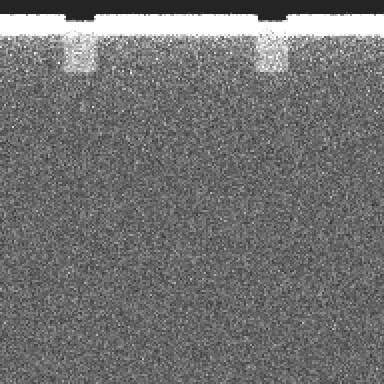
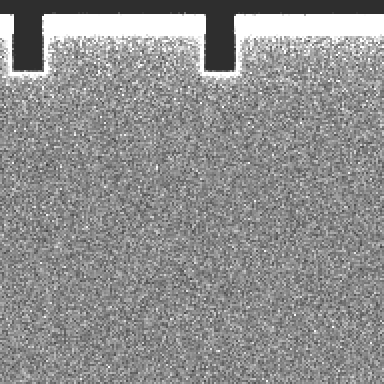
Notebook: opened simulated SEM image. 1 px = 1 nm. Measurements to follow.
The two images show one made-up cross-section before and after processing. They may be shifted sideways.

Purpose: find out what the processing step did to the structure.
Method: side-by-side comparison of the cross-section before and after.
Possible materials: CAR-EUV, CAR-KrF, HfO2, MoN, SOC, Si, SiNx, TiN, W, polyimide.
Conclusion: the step removed SOC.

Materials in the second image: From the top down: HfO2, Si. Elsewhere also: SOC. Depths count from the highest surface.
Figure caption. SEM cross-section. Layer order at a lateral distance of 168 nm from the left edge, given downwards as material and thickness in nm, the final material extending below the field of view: HfO2 18, Si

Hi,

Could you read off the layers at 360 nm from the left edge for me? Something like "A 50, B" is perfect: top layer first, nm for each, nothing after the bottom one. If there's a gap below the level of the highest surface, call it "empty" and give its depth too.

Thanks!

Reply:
HfO2 18, Si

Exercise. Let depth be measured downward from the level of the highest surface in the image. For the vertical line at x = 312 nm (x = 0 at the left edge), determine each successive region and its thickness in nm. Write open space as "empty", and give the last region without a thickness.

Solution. HfO2 18, Si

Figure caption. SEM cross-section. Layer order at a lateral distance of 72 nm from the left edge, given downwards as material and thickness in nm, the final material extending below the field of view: HfO2 18, Si